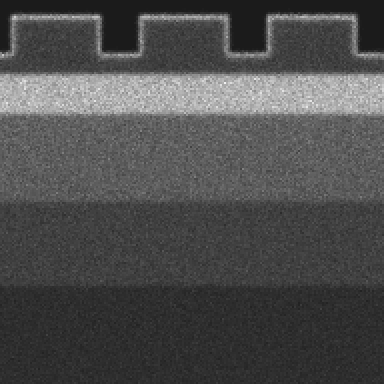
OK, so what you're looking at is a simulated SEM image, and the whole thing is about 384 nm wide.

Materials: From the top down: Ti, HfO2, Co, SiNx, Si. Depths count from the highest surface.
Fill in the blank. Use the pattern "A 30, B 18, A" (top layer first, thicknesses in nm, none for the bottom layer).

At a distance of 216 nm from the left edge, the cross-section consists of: Ti 58, HfO2 40, Co 88, SiNx 84, Si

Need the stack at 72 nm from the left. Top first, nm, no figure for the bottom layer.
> Ti 58, HfO2 40, Co 88, SiNx 84, Si